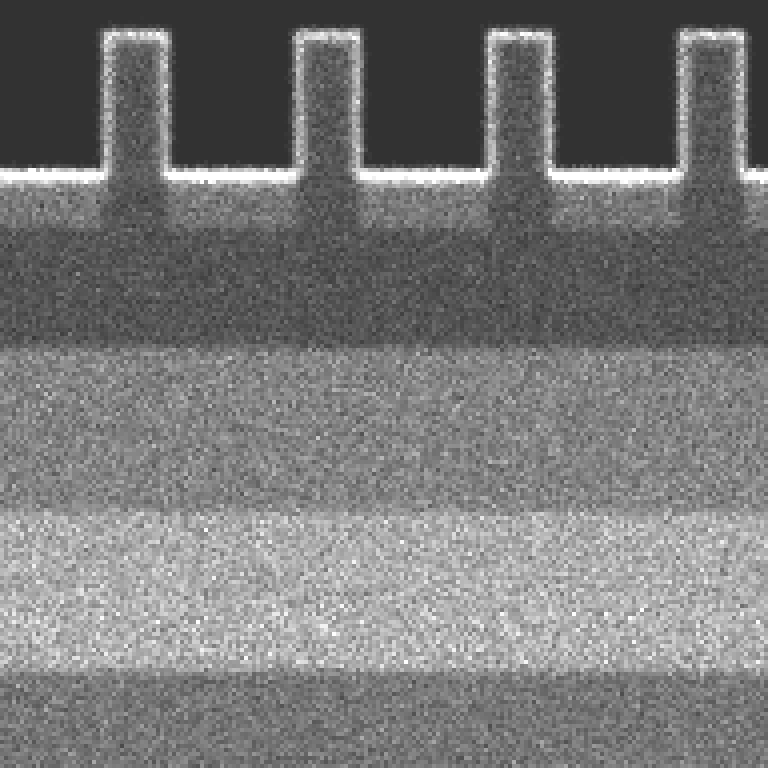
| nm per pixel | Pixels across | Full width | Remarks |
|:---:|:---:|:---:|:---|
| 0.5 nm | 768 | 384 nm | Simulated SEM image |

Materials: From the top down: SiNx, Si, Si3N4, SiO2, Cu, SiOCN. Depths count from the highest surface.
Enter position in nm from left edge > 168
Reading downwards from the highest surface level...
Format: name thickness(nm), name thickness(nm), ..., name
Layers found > Si 158, Si3N4 82, SiO2 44, Cu 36, SiOCN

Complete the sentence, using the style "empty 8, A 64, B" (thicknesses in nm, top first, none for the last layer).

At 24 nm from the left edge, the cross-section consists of empty 70, SiNx 28, Si 60, Si3N4 82, SiO2 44, Cu 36, SiOCN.